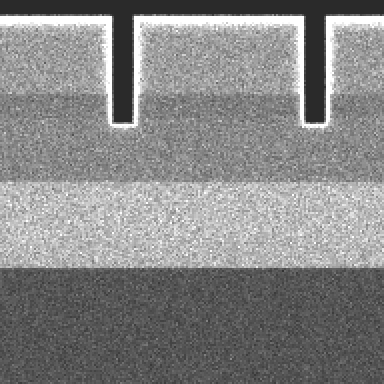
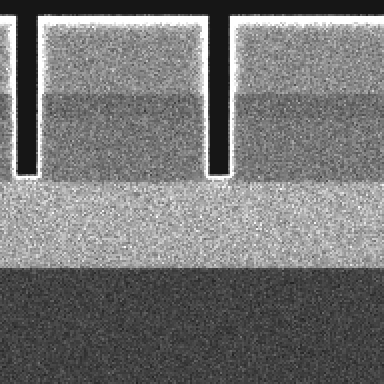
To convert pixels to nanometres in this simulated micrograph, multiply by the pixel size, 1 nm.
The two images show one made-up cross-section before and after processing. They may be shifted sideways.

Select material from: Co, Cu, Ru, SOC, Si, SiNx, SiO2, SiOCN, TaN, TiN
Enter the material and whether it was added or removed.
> TiN / removed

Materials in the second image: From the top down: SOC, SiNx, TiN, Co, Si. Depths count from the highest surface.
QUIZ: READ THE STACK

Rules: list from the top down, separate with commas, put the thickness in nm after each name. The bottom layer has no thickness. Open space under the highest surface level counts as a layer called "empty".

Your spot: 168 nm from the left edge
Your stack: SOC 78, SiNx 24, TiN 64, Co 86, Si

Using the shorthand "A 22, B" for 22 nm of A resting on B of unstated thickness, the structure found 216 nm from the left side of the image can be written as empty 160, TiN 6, Co 86, Si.